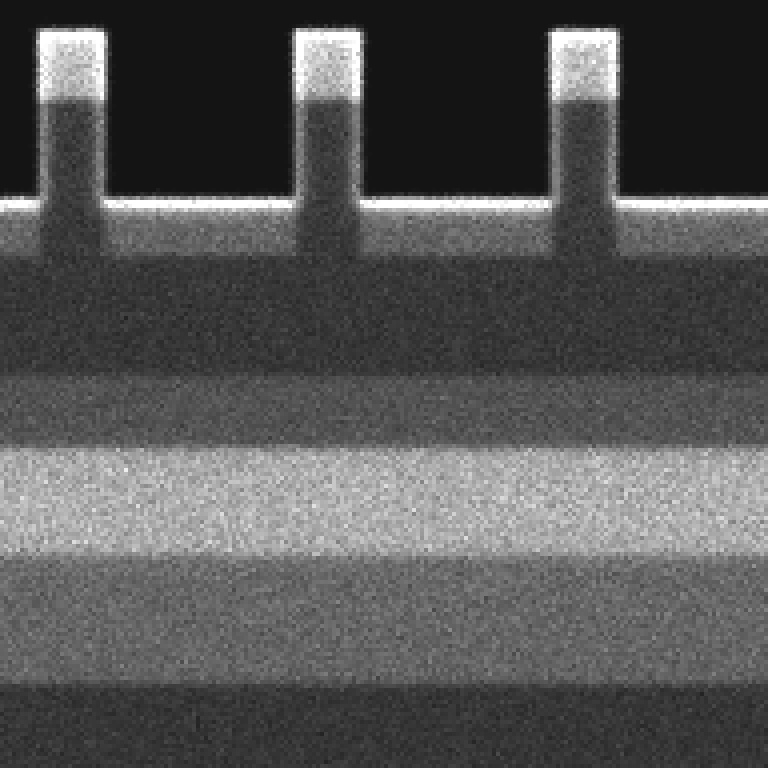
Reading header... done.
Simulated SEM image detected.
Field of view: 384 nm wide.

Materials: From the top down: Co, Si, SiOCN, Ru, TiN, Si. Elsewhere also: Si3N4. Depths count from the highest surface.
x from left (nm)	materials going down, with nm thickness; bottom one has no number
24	Co 34, Si 138, SiOCN 36, Ru 54, TiN 64, Si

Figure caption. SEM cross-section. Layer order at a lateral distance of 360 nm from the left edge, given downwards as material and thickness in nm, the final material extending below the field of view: empty 84, Si3N4 28, Si 60, SiOCN 36, Ru 54, TiN 64, Si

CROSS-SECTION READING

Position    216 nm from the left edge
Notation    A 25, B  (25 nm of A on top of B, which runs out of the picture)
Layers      empty 84, Si3N4 28, Si 60, SiOCN 36, Ru 54, TiN 64, Si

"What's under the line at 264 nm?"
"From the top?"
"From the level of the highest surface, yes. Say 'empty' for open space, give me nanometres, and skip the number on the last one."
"empty 84, Si3N4 28, Si 60, SiOCN 36, Ru 54, TiN 64, Si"